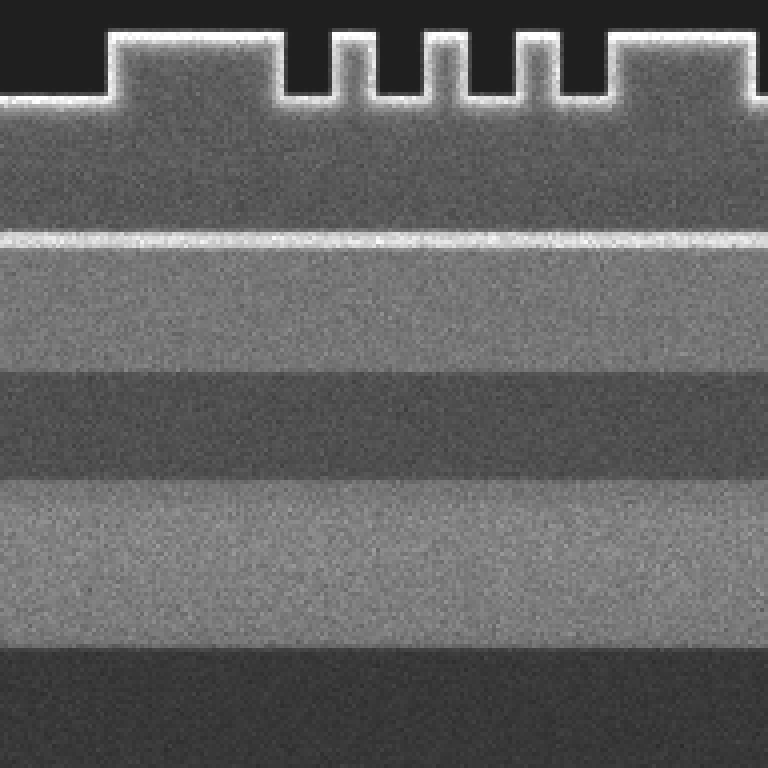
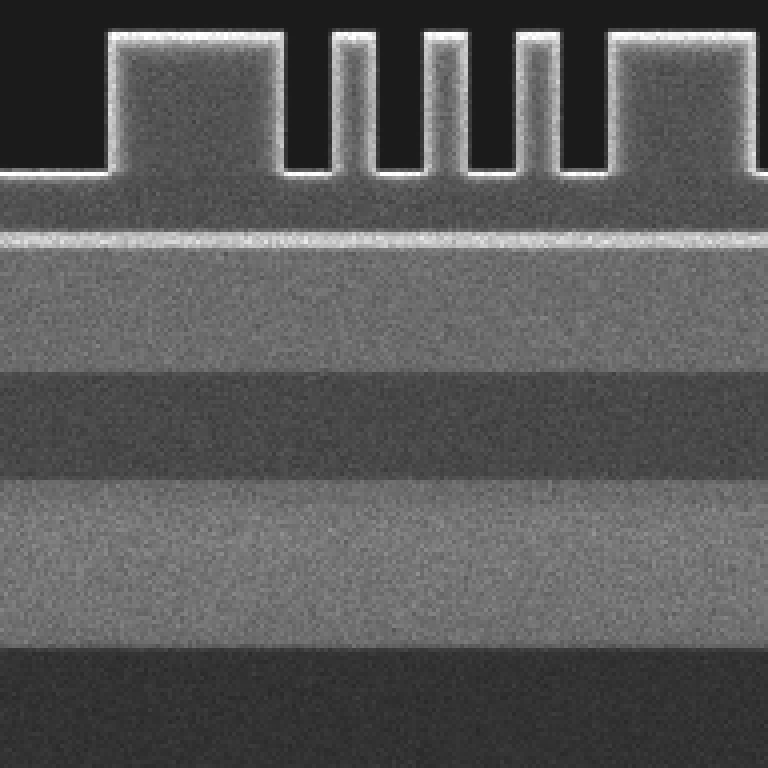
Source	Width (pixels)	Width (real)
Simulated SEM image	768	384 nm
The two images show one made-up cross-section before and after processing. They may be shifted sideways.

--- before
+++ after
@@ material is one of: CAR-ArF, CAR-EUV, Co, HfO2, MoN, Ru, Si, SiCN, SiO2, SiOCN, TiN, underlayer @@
underlayer removed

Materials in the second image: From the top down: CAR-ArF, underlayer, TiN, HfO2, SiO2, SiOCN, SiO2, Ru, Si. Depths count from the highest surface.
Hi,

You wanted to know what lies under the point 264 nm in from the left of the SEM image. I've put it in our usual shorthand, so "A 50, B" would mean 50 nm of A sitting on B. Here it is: CAR-ArF 32, underlayer 38, TiN 30, HfO2 8, SiO2 62, SiOCN 54, SiO2 12, Ru 72, Si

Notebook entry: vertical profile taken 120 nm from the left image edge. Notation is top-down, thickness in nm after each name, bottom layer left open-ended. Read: CAR-ArF 32, underlayer 38, TiN 30, HfO2 8, SiO2 62, SiOCN 54, SiO2 12, Ru 72, Si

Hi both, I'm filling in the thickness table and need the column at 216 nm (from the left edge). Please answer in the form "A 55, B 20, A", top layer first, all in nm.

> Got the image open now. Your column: CAR-ArF 32, underlayer 38, TiN 30, HfO2 8, SiO2 62, SiOCN 54, SiO2 12, Ru 72, Si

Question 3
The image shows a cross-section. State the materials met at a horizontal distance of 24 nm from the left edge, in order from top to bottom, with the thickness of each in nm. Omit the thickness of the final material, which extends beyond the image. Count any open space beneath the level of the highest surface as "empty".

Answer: empty 70, TiN 30, HfO2 8, SiO2 62, SiOCN 54, SiO2 12, Ru 72, Si